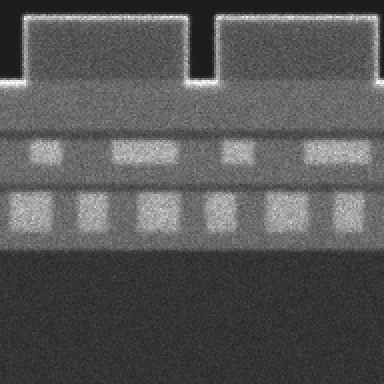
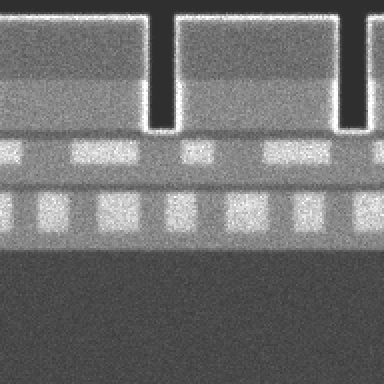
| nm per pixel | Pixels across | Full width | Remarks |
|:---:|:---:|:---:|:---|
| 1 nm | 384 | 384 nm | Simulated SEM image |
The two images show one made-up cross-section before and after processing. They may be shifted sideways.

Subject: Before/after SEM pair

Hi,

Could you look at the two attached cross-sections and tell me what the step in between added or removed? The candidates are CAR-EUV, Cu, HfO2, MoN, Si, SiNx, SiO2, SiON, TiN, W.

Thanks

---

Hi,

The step removed SiO2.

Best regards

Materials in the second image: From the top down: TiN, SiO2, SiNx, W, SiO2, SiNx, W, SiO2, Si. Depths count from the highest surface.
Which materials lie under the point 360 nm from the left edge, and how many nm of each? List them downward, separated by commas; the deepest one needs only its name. empty 114, SiNx 10, SiO2 44, SiNx 8, W 40, SiO2 18, Si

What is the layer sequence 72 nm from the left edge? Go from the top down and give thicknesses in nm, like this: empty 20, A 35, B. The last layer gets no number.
TiN 64, SiO2 50, SiNx 10, W 24, SiO2 20, SiNx 8, SiO2 58, Si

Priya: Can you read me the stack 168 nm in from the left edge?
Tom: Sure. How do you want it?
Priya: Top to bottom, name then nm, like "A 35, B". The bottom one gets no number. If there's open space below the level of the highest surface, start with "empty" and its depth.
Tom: empty 114, SiNx 10, SiO2 44, SiNx 8, W 40, SiO2 18, Si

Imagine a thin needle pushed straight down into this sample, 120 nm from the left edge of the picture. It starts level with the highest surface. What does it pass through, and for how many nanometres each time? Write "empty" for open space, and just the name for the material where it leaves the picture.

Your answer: TiN 64, SiO2 50, SiNx 10, W 24, SiO2 20, SiNx 8, W 40, SiO2 18, Si